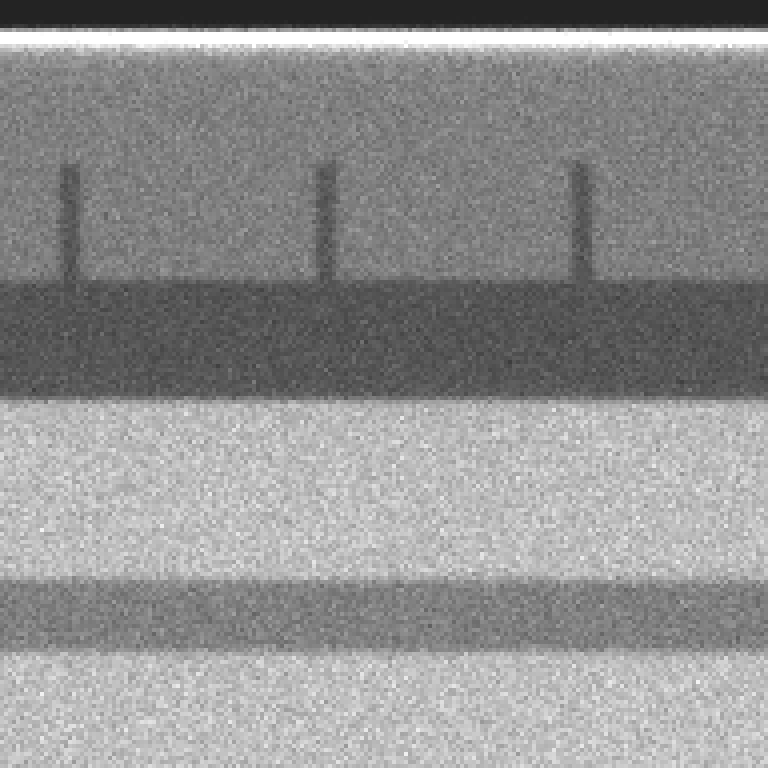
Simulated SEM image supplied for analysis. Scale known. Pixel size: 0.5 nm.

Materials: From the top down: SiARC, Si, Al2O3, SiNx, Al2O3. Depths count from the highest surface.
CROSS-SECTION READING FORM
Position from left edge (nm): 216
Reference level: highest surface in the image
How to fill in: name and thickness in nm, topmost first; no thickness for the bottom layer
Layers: SiARC 124, Si 60, Al2O3 90, SiNx 36, Al2O3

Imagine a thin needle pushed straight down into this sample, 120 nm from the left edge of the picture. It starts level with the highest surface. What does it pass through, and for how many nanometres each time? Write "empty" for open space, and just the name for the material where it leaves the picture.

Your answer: SiARC 124, Si 60, Al2O3 90, SiNx 36, Al2O3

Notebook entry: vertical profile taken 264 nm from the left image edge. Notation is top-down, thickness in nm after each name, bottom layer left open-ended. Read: SiARC 124, Si 60, Al2O3 90, SiNx 36, Al2O3